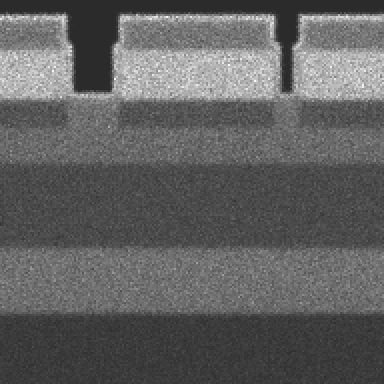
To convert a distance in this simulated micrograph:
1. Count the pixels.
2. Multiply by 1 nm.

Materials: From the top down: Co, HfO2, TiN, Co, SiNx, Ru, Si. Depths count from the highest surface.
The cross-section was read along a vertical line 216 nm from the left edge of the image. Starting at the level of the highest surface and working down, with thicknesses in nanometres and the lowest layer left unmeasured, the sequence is Co 34, HfO2 50, TiN 28, Co 36, SiNx 84, Ru 66, Si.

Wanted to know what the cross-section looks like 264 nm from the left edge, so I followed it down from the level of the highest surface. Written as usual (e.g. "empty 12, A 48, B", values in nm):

Co 34, HfO2 50, TiN 28, Co 36, SiNx 84, Ru 66, Si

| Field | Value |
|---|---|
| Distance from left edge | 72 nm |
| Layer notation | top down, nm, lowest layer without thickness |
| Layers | empty 78, Co 70, SiNx 84, Ru 66, Si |